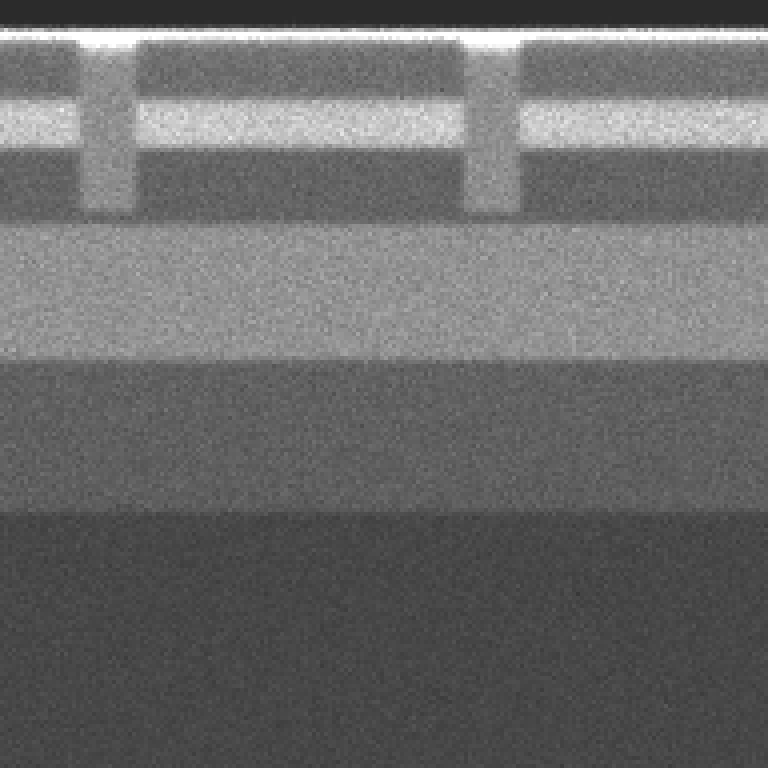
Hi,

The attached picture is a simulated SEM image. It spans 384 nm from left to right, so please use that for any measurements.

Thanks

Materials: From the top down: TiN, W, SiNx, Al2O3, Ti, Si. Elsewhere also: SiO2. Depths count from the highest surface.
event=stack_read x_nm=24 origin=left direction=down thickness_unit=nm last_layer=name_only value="TiN 34, W 24, SiNx 38, Al2O3 68, Ti 76, Si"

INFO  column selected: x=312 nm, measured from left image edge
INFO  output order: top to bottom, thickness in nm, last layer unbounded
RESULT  TiN 34, W 24, SiNx 38, Al2O3 68, Ti 76, Si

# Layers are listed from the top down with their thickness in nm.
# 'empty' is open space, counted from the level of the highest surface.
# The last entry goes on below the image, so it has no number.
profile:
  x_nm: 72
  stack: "TiN 34, W 24, SiNx 38, Al2O3 68, Ti 76, Si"